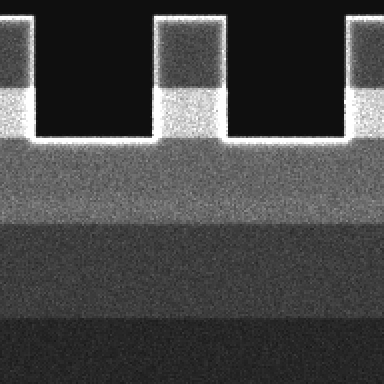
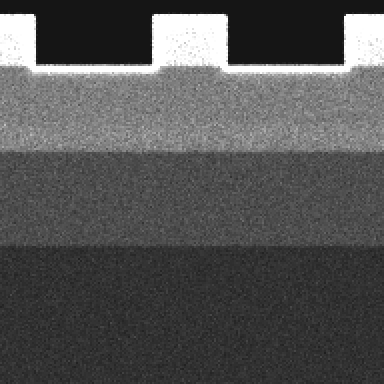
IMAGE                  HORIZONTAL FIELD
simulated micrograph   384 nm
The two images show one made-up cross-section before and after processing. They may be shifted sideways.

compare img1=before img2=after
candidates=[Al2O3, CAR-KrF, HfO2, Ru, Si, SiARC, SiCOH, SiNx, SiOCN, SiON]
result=removed:SiARC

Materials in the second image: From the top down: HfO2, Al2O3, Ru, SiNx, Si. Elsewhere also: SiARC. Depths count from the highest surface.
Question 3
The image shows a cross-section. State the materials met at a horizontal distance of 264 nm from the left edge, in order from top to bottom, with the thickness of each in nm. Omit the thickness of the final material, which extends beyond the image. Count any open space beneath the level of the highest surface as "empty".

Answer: empty 50, Al2O3 58, Ru 28, SiNx 94, Si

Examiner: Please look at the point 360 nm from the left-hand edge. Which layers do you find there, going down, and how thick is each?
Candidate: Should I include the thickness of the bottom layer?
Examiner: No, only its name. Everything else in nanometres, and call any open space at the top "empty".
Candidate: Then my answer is HfO2 50, Al2O3 58, Ru 28, SiNx 94, Si